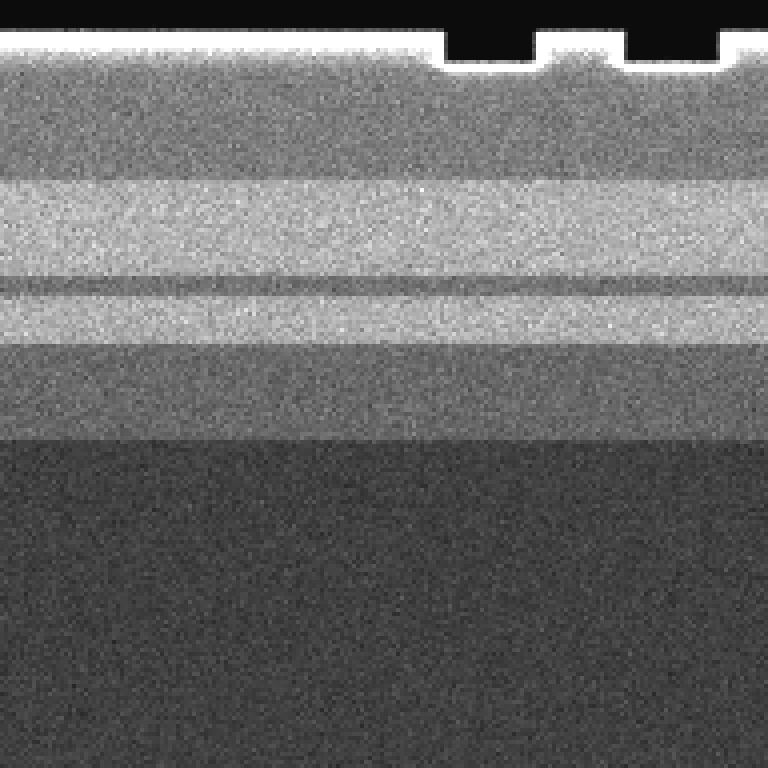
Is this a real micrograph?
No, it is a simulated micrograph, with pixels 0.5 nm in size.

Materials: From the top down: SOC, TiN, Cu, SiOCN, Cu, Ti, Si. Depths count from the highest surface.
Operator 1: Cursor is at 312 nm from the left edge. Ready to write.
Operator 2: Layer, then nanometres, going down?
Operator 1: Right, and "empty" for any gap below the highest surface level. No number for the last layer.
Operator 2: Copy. empty 16, TiN 58, Cu 48, SiOCN 10, Cu 24, Ti 48, Si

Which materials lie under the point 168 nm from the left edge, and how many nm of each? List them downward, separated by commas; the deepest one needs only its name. SOC 16, TiN 58, Cu 48, SiOCN 10, Cu 24, Ti 48, Si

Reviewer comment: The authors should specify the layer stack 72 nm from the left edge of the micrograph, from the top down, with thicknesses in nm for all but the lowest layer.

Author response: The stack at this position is SOC 16, TiN 58, Cu 48, SiOCN 10, Cu 24, Ti 48, Si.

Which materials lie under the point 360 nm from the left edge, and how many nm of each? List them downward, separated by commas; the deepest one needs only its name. SOC 16, TiN 58, Cu 48, SiOCN 10, Cu 24, Ti 48, Si